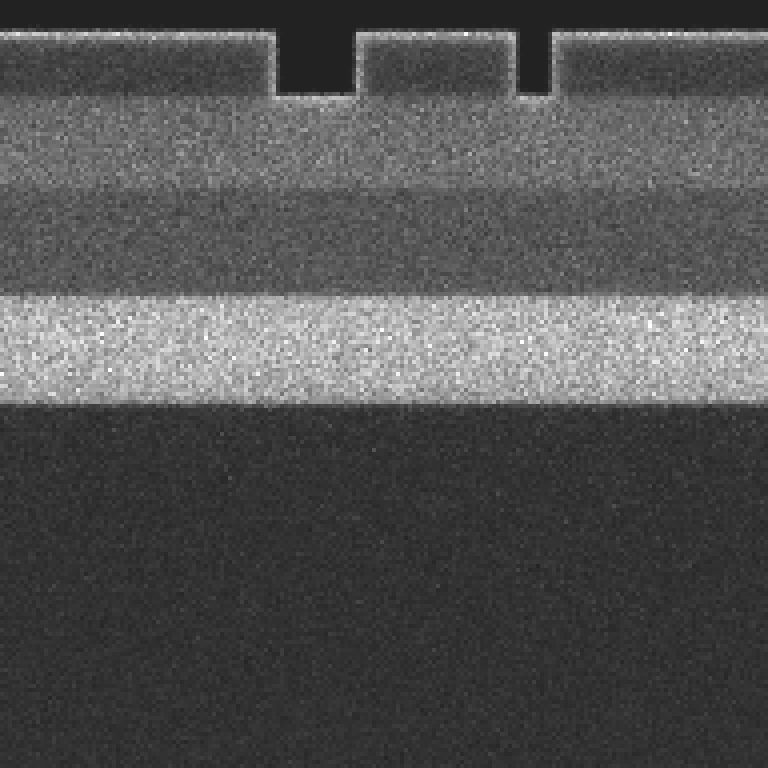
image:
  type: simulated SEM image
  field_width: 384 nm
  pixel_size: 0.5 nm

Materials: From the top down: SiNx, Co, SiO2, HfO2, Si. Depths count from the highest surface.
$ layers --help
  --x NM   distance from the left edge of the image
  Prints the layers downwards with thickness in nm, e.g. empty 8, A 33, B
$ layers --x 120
SiNx 32, Co 46, SiO2 54, HfO2 54, Si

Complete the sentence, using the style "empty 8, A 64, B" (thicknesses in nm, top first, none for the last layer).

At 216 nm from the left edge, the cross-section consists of SiNx 32, Co 46, SiO2 54, HfO2 54, Si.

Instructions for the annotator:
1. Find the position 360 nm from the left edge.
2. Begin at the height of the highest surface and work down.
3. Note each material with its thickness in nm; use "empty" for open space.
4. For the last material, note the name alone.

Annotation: SiNx 32, Co 46, SiO2 54, HfO2 54, Si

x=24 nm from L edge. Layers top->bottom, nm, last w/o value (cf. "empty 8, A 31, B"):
SiNx 32, Co 46, SiO2 54, HfO2 54, Si